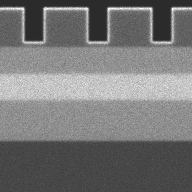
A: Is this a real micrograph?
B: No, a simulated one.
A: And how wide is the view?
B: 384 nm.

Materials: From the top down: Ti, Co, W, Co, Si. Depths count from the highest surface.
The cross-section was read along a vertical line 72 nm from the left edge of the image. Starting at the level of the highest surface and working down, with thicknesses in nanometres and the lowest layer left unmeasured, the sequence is empty 68, Ti 10, Co 54, W 52, Co 82, Si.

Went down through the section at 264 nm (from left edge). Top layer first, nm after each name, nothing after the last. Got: Ti 78, Co 54, W 52, Co 82, Si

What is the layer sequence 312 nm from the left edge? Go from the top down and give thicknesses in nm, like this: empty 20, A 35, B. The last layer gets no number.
empty 68, Ti 10, Co 54, W 52, Co 82, Si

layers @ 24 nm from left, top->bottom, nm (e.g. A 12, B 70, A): Ti 78, Co 54, W 52, Co 82, Si